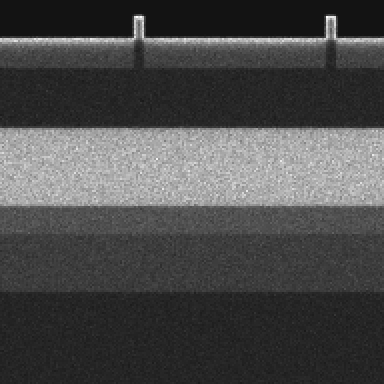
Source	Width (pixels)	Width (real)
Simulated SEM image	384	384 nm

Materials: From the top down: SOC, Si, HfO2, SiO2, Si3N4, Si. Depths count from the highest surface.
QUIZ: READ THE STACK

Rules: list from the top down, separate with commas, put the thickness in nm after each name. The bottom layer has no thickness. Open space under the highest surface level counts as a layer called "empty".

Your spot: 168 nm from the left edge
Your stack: empty 22, SOC 30, Si 60, HfO2 78, SiO2 28, Si3N4 58, Si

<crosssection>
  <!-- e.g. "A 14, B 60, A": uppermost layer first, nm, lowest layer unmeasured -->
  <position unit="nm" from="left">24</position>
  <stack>empty 22, SOC 30, Si 60, HfO2 78, SiO2 28, Si3N4 58, Si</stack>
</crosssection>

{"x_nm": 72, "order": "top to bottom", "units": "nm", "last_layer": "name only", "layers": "empty 22, SOC 30, Si 60, HfO2 78, SiO2 28, Si3N4 58, Si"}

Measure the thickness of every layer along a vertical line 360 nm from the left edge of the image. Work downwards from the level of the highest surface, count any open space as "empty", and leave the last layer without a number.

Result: empty 22, SOC 30, Si 60, HfO2 78, SiO2 28, Si3N4 58, Si